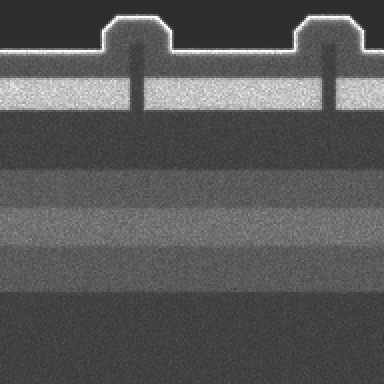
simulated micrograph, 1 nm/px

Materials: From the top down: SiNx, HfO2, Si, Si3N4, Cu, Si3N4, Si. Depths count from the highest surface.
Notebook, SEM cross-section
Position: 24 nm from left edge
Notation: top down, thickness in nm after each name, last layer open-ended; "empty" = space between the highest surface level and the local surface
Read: empty 34, SiNx 28, HfO2 32, Si 60, Si3N4 38, Cu 38, Si3N4 46, Si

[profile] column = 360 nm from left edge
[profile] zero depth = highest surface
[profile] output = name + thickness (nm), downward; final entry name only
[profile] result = empty 12, SiNx 50, HfO2 32, Si 60, Si3N4 38, Cu 38, Si3N4 46, Si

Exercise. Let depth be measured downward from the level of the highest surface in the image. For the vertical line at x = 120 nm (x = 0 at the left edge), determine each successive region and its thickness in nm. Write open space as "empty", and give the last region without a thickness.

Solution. SiNx 62, HfO2 32, Si 60, Si3N4 38, Cu 38, Si3N4 46, Si